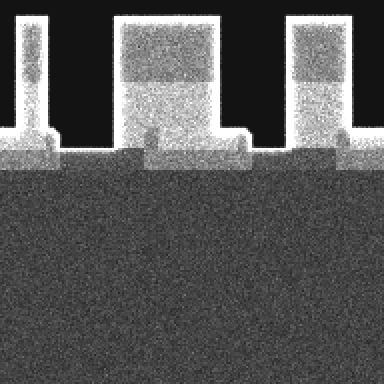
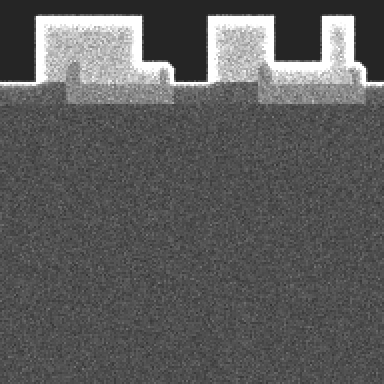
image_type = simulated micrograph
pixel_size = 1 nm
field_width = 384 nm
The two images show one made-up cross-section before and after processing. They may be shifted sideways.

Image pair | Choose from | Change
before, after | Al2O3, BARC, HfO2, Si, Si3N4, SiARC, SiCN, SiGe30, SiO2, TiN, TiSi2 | SiARC (removed)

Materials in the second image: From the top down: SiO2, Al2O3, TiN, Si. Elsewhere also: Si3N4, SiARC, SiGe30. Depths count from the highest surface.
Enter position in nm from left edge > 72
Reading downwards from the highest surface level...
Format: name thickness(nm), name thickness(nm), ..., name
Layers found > SiO2 46, Si3N4 42, Si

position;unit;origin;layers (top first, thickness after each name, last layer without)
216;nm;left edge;SiO2 66, SiGe30 22, Si